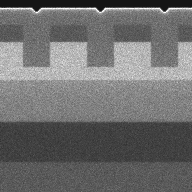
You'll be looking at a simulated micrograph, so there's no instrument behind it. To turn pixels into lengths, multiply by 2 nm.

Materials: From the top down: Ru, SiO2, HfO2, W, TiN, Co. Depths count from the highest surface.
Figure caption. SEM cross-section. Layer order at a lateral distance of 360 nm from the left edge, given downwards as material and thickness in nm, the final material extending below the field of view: Ru 34, SiO2 34, HfO2 76, W 84, TiN 80, Co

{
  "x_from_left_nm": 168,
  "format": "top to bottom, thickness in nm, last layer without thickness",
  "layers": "Ru 34, SiO2 34, HfO2 76, W 84, TiN 80, Co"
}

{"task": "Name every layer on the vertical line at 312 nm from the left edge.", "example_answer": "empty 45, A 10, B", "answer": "Ru 118, HfO2 26, W 84, TiN 80, Co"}